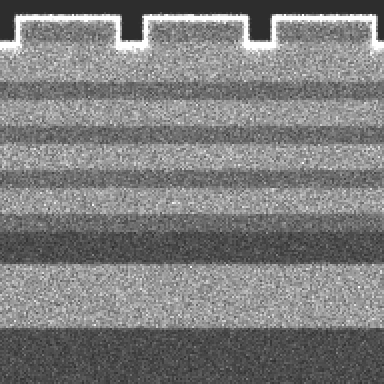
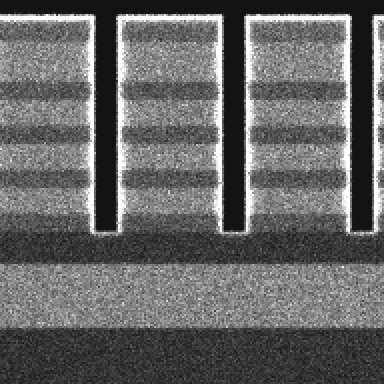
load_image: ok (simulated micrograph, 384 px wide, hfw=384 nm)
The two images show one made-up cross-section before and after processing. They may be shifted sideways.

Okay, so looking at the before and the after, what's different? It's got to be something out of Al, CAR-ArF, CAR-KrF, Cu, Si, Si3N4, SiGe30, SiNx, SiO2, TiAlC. SiNx and SiO2, removed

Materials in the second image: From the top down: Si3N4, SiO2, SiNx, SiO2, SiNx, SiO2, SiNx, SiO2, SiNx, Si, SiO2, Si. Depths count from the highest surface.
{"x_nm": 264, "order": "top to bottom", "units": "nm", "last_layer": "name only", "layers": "Si3N4 26, SiO2 40, SiNx 18, SiO2 26, SiNx 18, SiO2 26, SiNx 18, SiO2 26, SiNx 18, Si 32, SiO2 64, Si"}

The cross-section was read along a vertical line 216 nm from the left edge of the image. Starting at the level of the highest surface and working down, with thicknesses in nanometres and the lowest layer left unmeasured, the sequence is Si3N4 26, SiO2 40, SiNx 18, SiO2 26, SiNx 18, SiO2 26, SiNx 18, SiO2 26, SiNx 18, Si 32, SiO2 64, Si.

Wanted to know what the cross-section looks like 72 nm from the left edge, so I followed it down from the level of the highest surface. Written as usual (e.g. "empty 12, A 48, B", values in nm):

Si3N4 26, SiO2 40, SiNx 18, SiO2 26, SiNx 18, SiO2 26, SiNx 18, SiO2 26, SiNx 18, Si 32, SiO2 64, Si